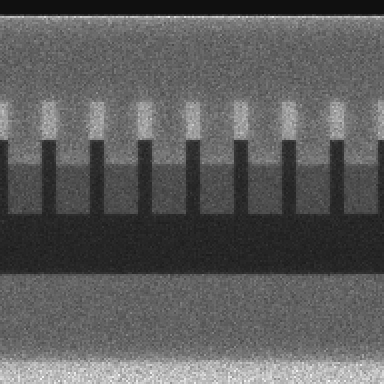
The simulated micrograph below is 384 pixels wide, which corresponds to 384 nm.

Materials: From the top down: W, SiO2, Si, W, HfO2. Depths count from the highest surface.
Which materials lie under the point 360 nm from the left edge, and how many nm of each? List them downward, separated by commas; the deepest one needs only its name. W 148, SiO2 50, Si 60, W 88, HfO2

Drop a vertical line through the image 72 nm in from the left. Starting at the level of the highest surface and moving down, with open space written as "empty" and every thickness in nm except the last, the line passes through W 148, SiO2 50, Si 60, W 88, HfO2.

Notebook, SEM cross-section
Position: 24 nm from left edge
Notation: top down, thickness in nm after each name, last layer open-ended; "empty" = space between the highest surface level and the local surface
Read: W 148, SiO2 50, Si 60, W 88, HfO2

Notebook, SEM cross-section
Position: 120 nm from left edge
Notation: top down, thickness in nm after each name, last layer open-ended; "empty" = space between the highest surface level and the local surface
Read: W 148, SiO2 50, Si 60, W 88, HfO2